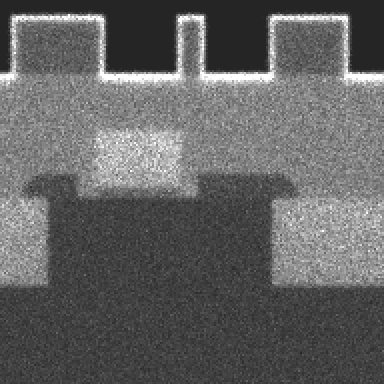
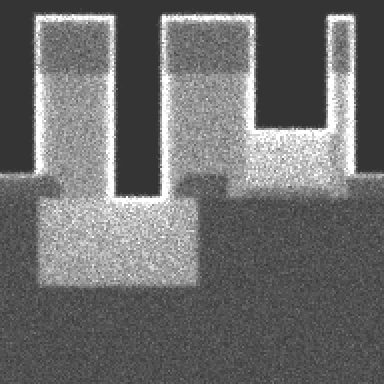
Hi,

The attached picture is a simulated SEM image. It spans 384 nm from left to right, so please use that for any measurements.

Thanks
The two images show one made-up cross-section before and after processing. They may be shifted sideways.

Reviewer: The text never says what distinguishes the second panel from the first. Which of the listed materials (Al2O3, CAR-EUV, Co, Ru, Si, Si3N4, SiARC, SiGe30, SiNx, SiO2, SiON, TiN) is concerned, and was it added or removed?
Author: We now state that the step removed SiO2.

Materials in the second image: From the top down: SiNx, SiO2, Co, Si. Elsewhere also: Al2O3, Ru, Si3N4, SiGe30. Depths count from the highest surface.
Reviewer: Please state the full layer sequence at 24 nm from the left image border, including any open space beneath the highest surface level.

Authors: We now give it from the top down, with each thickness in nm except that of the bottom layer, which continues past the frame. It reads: empty 158, SiGe30 24, Si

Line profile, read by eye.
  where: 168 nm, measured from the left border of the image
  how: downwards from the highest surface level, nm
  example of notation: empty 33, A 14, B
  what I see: SiNx 58, SiO2 124, Co 88, Si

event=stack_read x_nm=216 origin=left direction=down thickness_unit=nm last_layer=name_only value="SiNx 58, SiO2 100, SiGe30 24, Si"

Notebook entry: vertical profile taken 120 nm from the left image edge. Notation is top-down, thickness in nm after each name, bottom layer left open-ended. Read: empty 182, Co 88, Si